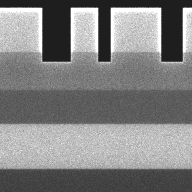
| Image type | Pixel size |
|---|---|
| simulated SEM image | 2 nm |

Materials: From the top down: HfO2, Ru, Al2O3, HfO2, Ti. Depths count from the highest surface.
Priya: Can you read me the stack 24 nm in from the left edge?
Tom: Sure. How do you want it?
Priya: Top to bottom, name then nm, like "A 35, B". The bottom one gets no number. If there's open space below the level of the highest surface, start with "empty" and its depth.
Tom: HfO2 88, Ru 76, Al2O3 68, HfO2 90, Ti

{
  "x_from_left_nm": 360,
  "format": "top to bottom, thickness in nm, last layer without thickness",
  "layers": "empty 108, Ru 56, Al2O3 68, HfO2 90, Ti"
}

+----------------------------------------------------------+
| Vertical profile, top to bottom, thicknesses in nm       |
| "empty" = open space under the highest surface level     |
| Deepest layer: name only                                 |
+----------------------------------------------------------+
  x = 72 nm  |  HfO2 88, Ru 76, Al2O3 68, HfO2 90, Ti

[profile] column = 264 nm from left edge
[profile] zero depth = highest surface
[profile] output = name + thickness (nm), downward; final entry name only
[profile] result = HfO2 88, Ru 76, Al2O3 68, HfO2 90, Ti